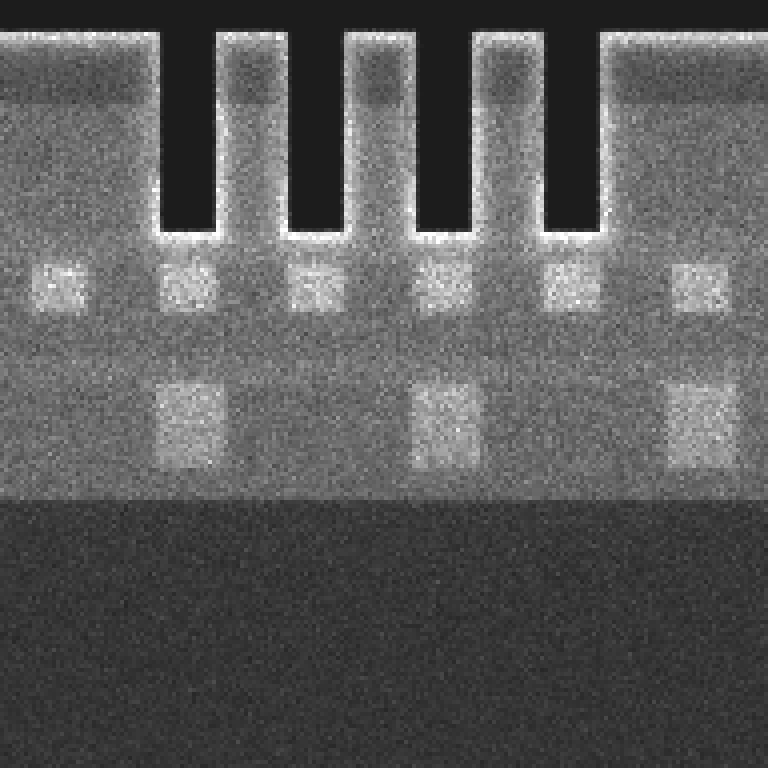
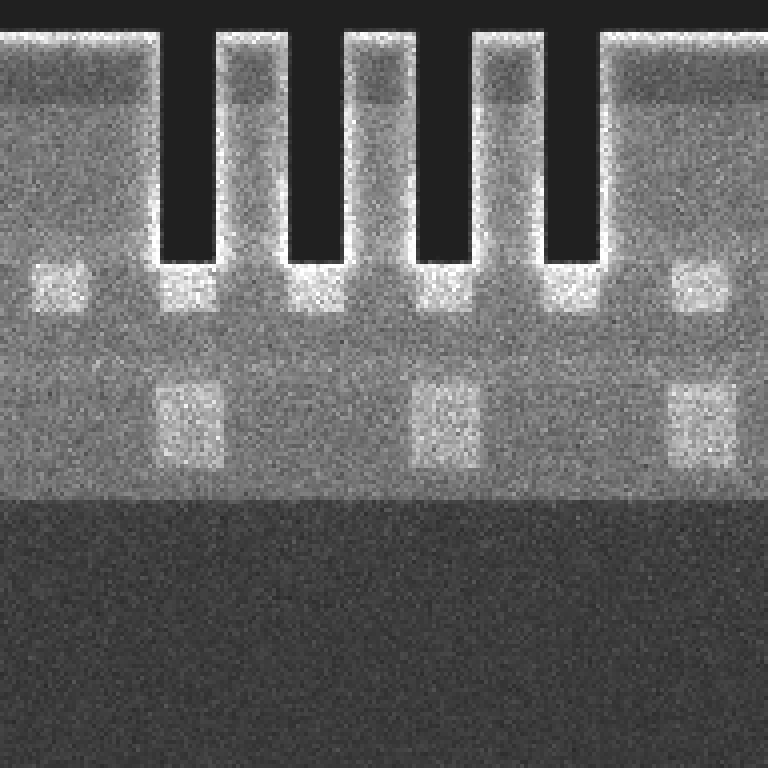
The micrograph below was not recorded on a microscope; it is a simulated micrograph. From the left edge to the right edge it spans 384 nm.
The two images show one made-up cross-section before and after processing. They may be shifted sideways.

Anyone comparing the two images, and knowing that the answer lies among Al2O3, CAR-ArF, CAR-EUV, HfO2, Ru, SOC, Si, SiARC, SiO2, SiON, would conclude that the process removed Al2O3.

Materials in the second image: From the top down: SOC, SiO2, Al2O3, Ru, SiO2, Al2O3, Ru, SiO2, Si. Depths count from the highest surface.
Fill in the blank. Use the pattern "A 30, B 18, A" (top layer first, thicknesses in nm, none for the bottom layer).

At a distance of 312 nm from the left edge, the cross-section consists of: SOC 36, SiO2 64, Al2O3 16, SiO2 46, Al2O3 14, SiO2 58, Si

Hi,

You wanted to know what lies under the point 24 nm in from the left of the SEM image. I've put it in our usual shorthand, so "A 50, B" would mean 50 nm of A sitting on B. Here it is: SOC 36, SiO2 64, Al2O3 16, Ru 24, SiO2 22, Al2O3 14, SiO2 58, Si